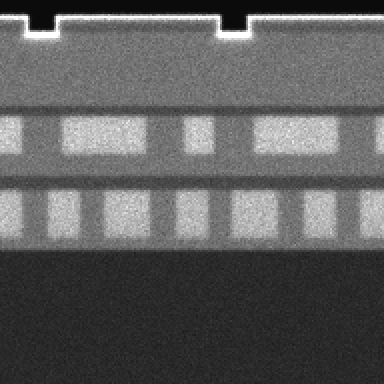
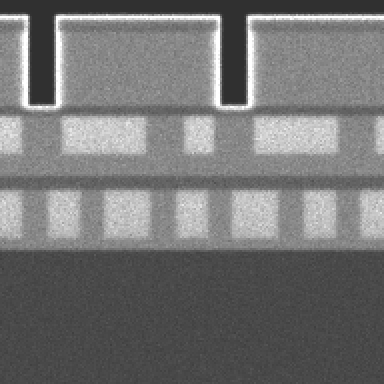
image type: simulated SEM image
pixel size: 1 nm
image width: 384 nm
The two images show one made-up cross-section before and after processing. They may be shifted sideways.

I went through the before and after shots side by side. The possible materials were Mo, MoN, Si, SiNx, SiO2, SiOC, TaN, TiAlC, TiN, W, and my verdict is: removed, SiO2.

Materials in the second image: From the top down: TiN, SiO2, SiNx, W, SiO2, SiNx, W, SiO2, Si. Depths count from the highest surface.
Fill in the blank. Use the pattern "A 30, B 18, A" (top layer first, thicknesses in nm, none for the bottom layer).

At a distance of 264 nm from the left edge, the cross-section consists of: TiN 16, SiO2 74, SiNx 10, W 38, SiO2 22, SiNx 14, W 48, SiO2 12, Si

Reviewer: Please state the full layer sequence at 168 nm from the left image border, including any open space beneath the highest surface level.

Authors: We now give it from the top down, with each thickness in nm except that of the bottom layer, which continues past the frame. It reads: TiN 16, SiO2 74, SiNx 10, SiO2 60, SiNx 14, SiO2 60, Si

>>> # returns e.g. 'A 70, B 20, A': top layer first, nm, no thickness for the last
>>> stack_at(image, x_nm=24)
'TiN 16, SiO2 74, SiNx 10, SiO2 60, SiNx 14, SiO2 60, Si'